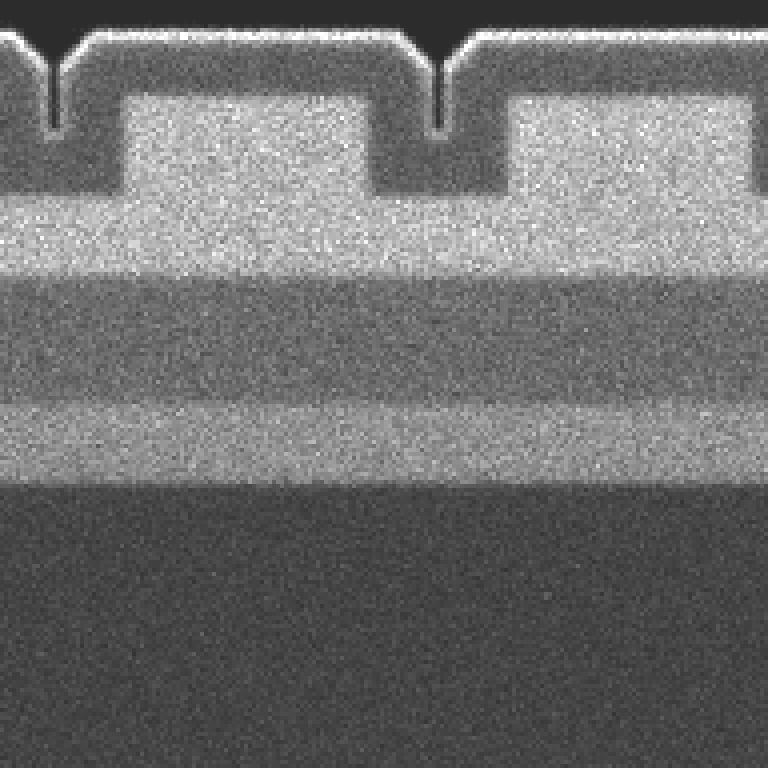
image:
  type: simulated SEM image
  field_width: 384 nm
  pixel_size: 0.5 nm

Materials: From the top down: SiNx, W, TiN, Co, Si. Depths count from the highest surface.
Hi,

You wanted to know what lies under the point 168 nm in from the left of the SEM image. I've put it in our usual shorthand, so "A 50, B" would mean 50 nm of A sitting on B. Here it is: SiNx 32, W 90, TiN 64, Co 40, Si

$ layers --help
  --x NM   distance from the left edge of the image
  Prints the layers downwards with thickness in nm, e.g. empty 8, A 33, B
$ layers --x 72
SiNx 32, W 90, TiN 64, Co 40, Si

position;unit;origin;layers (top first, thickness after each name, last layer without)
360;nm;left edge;SiNx 32, W 90, TiN 64, Co 40, Si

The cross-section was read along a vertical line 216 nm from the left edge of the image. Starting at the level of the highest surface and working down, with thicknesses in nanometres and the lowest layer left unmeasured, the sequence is empty 50, SiNx 32, W 40, TiN 64, Co 40, Si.